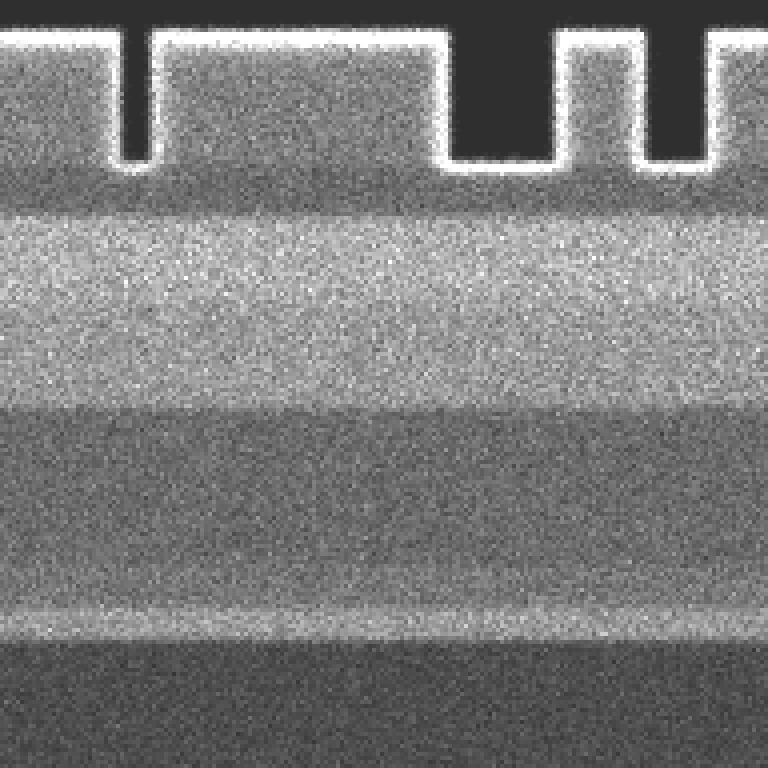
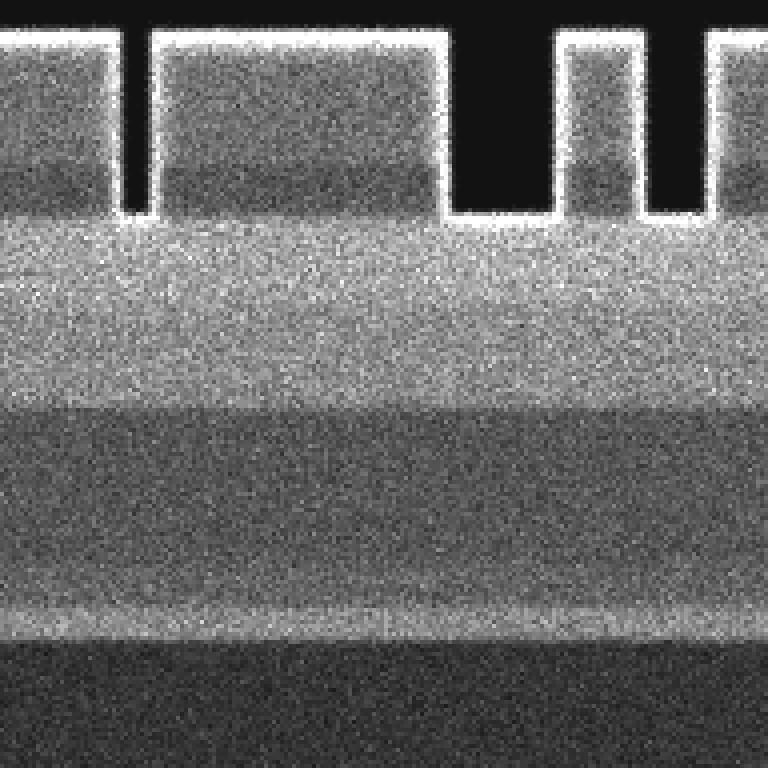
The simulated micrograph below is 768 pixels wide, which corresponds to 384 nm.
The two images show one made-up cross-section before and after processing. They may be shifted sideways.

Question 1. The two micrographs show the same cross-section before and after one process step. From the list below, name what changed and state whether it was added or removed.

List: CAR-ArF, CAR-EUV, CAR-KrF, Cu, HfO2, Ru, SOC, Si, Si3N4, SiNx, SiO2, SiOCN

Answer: SiNx, removed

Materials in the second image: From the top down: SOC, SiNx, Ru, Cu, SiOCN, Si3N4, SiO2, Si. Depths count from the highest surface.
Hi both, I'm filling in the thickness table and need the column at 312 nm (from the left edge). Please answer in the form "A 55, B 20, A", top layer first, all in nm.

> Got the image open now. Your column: SOC 66, SiNx 26, Ru 44, Cu 52, SiOCN 78, Si3N4 22, SiO2 16, Si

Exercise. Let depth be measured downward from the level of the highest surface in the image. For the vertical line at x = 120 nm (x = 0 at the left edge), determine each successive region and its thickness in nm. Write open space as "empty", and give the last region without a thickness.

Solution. SOC 66, SiNx 26, Ru 44, Cu 52, SiOCN 78, Si3N4 22, SiO2 16, Si